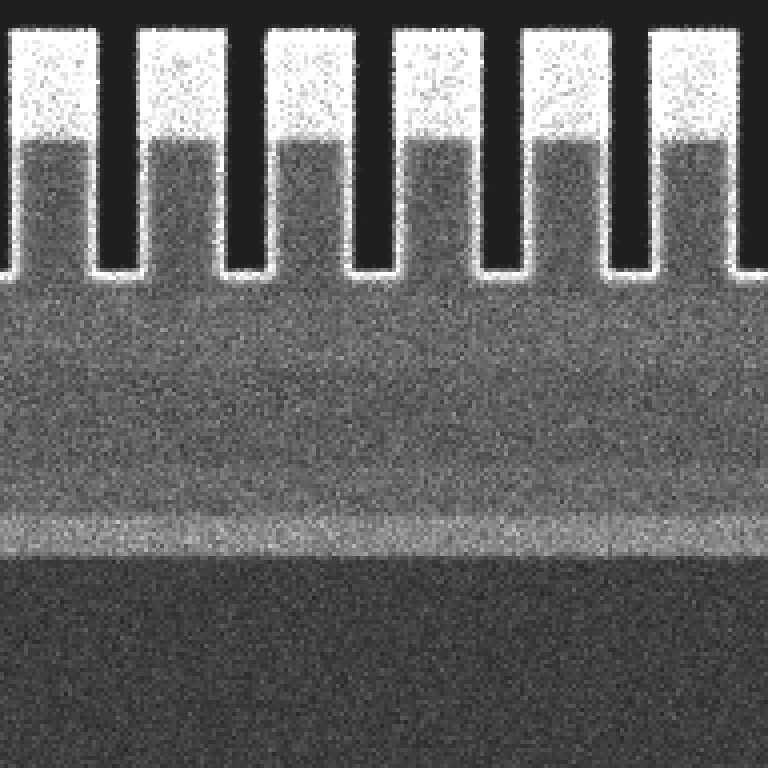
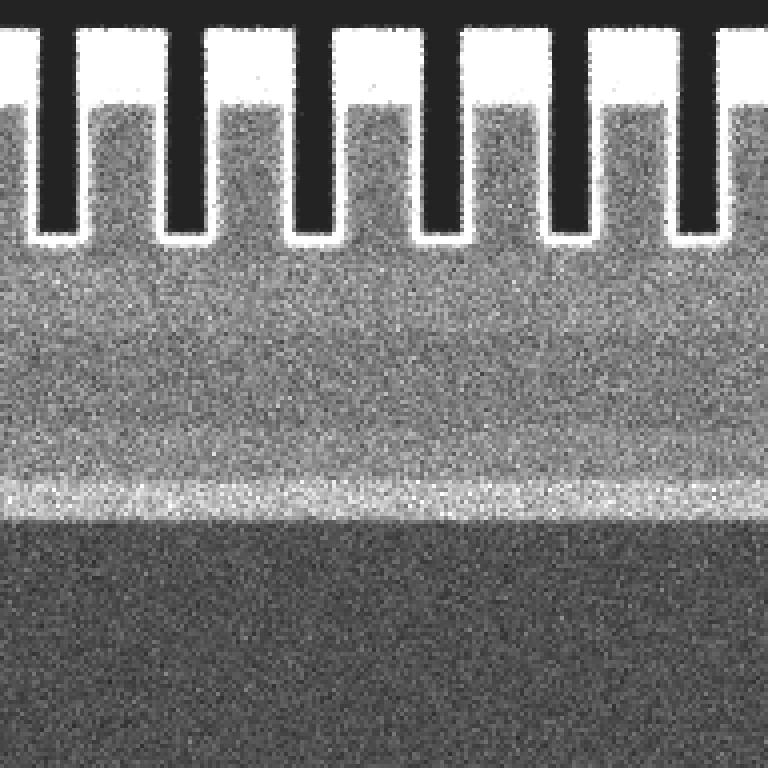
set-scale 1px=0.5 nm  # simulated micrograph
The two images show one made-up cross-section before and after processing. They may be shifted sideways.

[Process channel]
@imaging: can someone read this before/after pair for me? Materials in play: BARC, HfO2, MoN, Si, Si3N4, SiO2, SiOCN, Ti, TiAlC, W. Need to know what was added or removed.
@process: W removed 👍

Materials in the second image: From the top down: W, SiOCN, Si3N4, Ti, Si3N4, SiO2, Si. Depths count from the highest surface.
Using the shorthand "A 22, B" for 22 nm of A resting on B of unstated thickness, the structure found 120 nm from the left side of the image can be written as W 36, SiOCN 78, Si3N4 36, Ti 48, Si3N4 26, SiO2 20, Si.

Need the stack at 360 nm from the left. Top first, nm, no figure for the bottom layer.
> W 36, SiOCN 78, Si3N4 36, Ti 48, Si3N4 26, SiO2 20, Si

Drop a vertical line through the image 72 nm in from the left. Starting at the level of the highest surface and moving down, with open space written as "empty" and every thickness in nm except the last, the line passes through W 36, SiOCN 78, Si3N4 36, Ti 48, Si3N4 26, SiO2 20, Si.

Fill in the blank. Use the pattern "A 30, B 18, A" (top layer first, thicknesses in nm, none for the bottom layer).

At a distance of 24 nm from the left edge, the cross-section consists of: empty 102, SiOCN 12, Si3N4 36, Ti 48, Si3N4 26, SiO2 20, Si